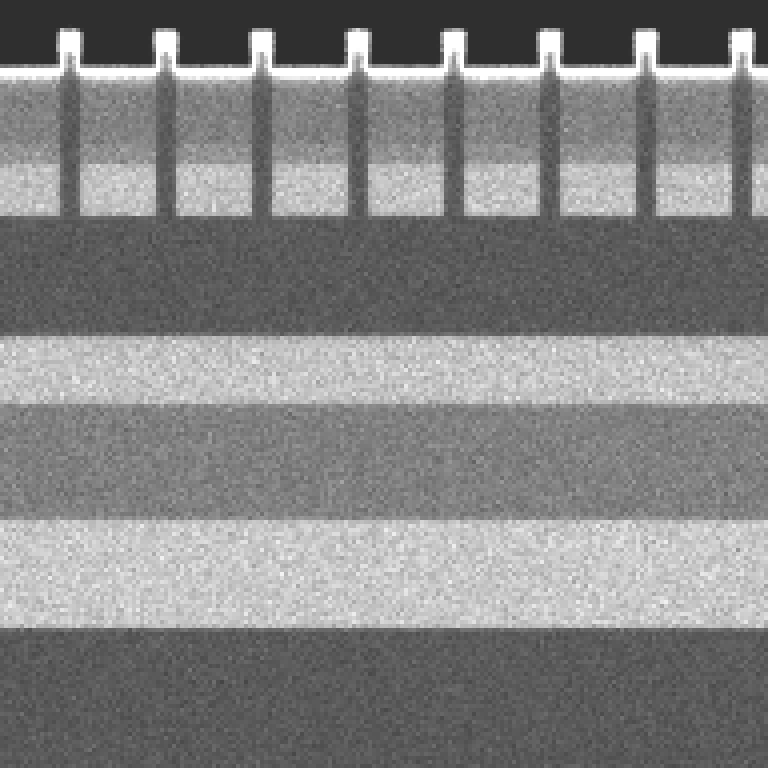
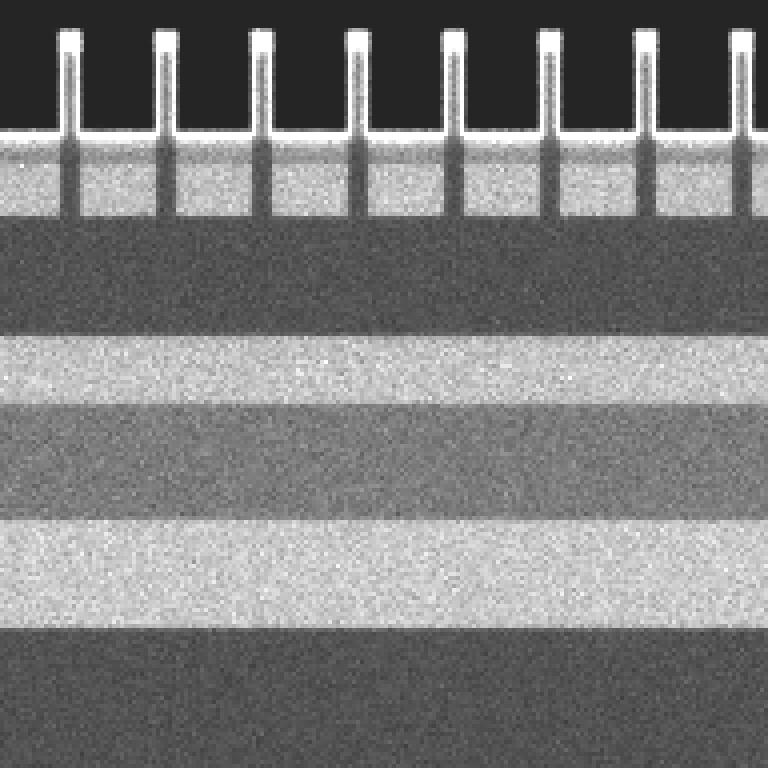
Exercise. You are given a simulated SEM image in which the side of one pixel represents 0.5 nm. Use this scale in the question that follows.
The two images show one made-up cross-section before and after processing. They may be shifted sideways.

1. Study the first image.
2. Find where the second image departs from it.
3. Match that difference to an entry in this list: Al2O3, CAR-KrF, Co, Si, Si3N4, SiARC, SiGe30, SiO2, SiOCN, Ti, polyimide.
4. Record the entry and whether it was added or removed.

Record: SiOCN / removed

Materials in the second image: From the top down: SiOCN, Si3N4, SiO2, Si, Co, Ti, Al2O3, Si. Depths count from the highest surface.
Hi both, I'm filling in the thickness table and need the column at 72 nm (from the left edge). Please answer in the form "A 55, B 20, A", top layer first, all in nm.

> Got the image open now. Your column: empty 50, SiOCN 6, Si3N4 10, SiO2 26, Si 60, Co 34, Ti 58, Al2O3 54, Si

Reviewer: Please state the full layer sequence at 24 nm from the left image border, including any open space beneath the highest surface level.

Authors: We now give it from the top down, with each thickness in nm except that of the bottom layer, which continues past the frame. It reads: empty 50, SiOCN 6, Si3N4 10, SiO2 26, Si 60, Co 34, Ti 58, Al2O3 54, Si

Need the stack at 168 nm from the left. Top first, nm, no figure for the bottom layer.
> empty 50, SiOCN 6, Si3N4 10, SiO2 26, Si 60, Co 34, Ti 58, Al2O3 54, Si